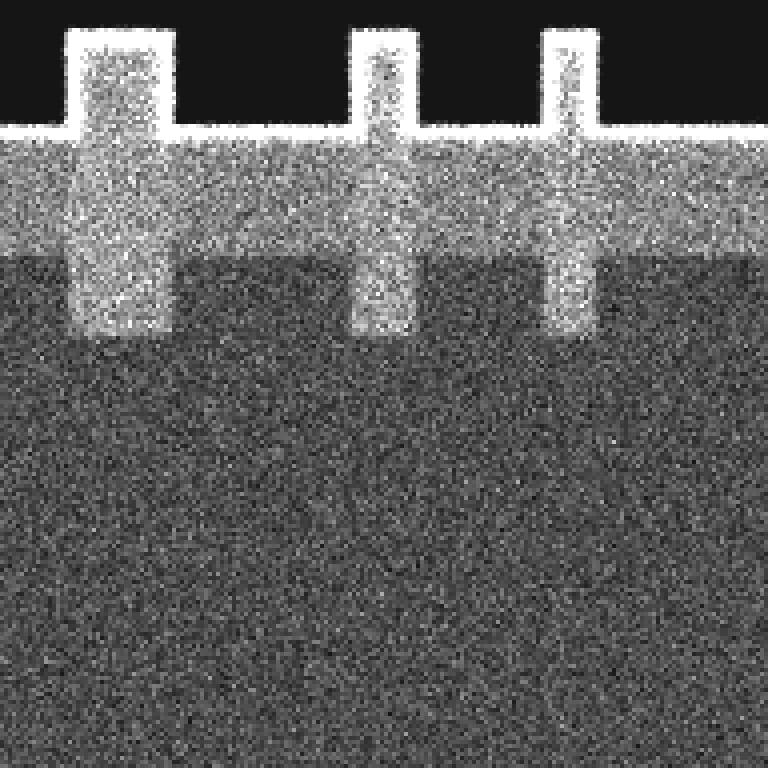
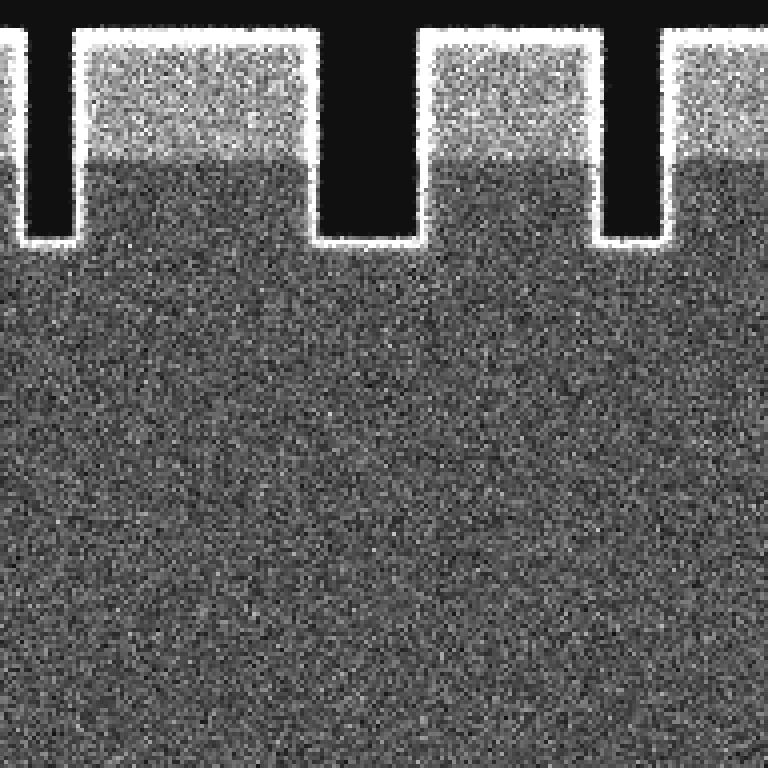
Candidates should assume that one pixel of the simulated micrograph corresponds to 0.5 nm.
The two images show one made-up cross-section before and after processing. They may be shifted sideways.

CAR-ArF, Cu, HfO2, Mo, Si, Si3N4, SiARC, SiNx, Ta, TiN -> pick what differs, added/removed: SiARC removed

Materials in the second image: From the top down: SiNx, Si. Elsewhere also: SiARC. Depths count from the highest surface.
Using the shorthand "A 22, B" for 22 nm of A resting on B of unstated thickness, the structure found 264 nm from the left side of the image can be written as SiNx 64, Si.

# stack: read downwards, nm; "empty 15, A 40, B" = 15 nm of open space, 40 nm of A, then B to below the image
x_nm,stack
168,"empty 104, Si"